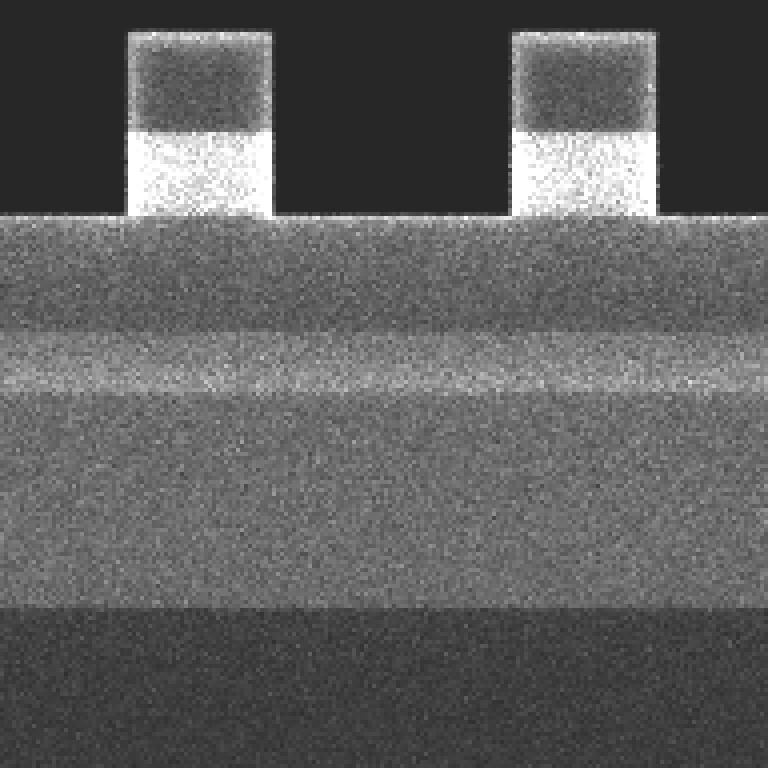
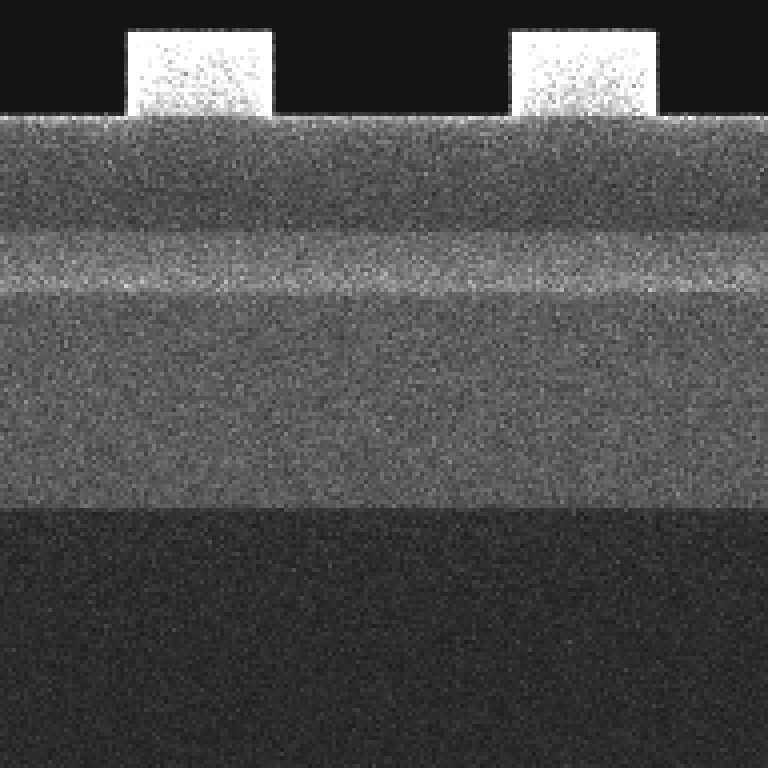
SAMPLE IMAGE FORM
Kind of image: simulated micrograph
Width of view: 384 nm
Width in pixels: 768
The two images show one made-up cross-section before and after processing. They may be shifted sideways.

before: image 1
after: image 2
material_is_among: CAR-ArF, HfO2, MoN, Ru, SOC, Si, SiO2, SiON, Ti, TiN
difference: SOC, removed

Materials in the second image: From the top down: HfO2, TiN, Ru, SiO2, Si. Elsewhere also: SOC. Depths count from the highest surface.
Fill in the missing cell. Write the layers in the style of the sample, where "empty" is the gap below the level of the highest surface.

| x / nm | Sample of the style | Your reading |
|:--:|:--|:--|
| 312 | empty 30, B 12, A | HfO2 42, TiN 58, Ru 30, SiO2 108, Si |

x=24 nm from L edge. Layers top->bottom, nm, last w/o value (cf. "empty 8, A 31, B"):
empty 42, TiN 58, Ru 30, SiO2 108, Si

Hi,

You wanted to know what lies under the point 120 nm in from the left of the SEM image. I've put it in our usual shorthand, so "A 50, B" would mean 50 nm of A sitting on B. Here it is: HfO2 42, TiN 58, Ru 30, SiO2 108, Si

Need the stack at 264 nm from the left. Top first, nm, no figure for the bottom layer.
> HfO2 42, TiN 58, Ru 30, SiO2 108, Si